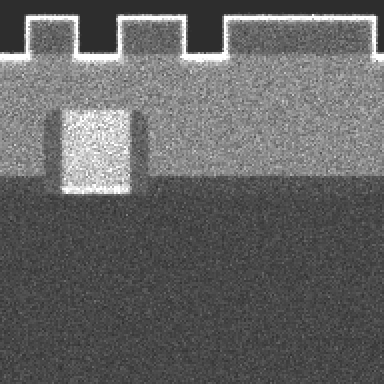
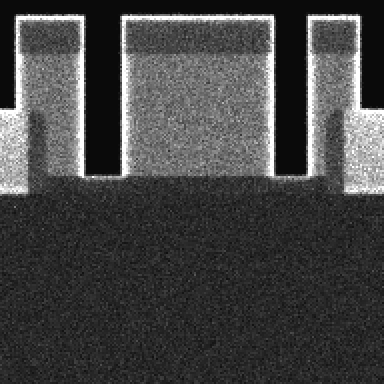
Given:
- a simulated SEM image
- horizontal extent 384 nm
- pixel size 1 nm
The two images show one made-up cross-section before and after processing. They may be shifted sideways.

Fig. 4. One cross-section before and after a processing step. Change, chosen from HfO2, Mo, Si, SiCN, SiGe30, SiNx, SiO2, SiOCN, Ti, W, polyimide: SiO2 removed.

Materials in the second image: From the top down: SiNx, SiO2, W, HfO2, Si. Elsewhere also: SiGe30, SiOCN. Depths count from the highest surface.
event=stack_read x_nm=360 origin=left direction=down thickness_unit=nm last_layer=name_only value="empty 94, W 76, HfO2 8, Si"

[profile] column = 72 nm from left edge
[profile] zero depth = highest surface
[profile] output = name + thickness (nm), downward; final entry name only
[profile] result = SiNx 38, SiO2 122, SiGe30 18, Si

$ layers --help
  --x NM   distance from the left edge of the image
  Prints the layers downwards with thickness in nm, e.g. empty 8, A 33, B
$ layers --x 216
SiNx 38, SiO2 122, SiGe30 18, Si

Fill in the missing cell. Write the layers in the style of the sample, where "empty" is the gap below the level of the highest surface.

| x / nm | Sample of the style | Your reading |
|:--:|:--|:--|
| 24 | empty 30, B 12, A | SiNx 38, SiO2 56, W 76, HfO2 8, Si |